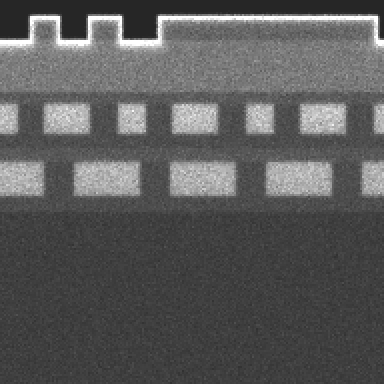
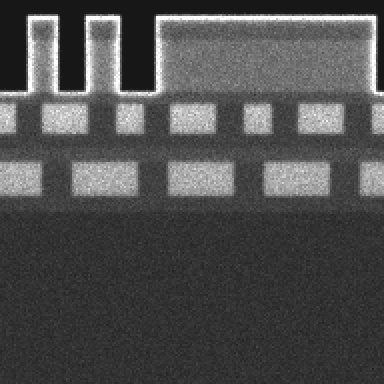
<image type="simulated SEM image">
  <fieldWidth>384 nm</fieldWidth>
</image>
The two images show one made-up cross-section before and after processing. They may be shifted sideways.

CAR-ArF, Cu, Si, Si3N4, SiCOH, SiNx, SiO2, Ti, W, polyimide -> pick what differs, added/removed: SiO2 removed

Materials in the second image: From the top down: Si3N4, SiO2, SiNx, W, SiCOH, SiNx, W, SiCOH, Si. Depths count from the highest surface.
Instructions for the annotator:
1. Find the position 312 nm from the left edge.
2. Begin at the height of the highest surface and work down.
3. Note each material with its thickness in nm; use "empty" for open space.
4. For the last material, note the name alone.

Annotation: Si3N4 24, SiO2 52, SiNx 12, W 30, SiCOH 14, SiNx 14, W 34, SiCOH 16, Si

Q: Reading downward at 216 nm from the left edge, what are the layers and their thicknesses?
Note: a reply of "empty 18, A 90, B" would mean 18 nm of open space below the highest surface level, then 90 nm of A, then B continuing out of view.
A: Si3N4 24, SiO2 52, SiNx 12, SiCOH 44, SiNx 14, W 34, SiCOH 16, Si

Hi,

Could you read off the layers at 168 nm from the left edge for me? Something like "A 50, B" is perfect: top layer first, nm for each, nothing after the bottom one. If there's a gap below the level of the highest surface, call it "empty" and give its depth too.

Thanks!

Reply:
Si3N4 24, SiO2 52, SiNx 12, SiCOH 44, SiNx 14, W 34, SiCOH 16, Si